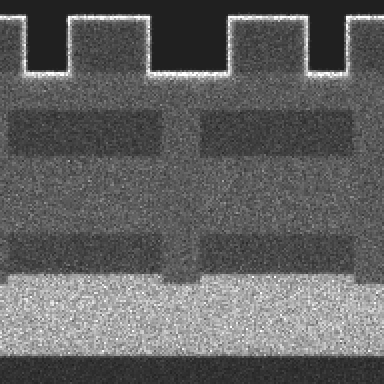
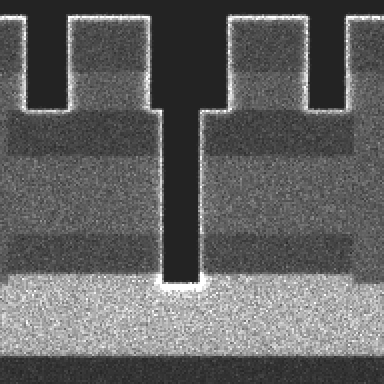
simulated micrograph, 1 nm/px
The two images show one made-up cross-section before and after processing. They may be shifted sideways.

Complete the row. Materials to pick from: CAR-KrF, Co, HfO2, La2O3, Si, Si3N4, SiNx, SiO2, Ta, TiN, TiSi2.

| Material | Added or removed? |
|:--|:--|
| SiO2 | removed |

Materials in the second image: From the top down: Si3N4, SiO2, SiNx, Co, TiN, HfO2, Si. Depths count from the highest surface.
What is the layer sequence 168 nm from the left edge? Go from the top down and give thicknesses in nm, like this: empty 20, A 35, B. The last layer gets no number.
empty 268, HfO2 72, Si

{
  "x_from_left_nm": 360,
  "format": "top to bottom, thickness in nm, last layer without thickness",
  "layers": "Si3N4 56, SiO2 212, HfO2 72, Si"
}